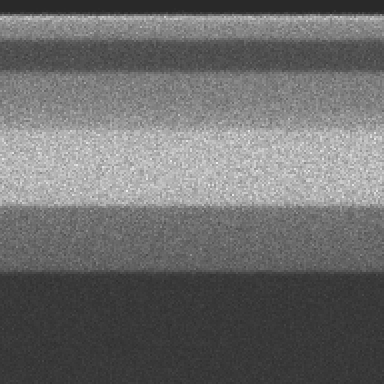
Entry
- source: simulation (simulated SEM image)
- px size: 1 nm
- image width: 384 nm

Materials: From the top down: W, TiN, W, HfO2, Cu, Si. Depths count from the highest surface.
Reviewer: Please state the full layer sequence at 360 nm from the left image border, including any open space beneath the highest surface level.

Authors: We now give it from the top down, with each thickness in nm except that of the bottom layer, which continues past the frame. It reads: W 24, TiN 32, W 58, HfO2 76, Cu 66, Si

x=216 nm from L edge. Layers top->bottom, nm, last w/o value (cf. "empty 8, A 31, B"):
W 24, TiN 32, W 58, HfO2 76, Cu 66, Si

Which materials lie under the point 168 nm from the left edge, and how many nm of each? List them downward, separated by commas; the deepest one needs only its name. W 24, TiN 32, W 58, HfO2 76, Cu 66, Si